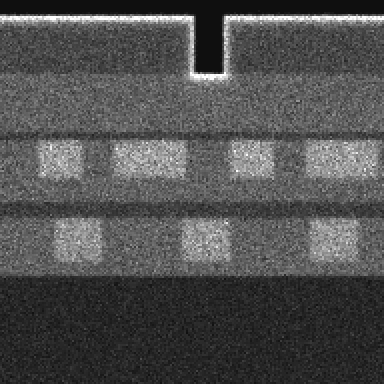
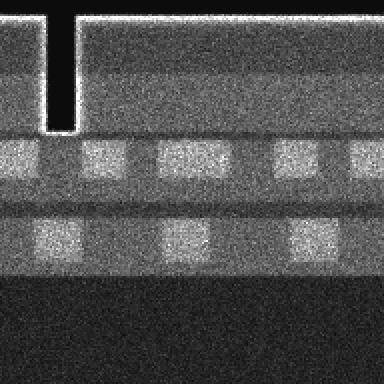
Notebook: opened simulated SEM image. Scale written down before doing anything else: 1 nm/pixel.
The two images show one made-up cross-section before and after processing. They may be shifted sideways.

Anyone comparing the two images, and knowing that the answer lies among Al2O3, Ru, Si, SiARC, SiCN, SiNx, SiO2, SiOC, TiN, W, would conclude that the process removed SiO2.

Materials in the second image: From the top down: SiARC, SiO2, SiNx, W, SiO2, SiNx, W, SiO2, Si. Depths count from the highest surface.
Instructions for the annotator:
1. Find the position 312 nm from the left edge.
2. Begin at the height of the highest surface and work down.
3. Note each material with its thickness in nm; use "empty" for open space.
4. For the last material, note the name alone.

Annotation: SiARC 58, SiO2 58, SiNx 8, W 38, SiO2 24, SiNx 16, W 44, SiO2 14, Si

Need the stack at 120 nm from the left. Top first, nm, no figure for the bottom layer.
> SiARC 58, SiO2 58, SiNx 8, W 38, SiO2 24, SiNx 16, SiO2 58, Si